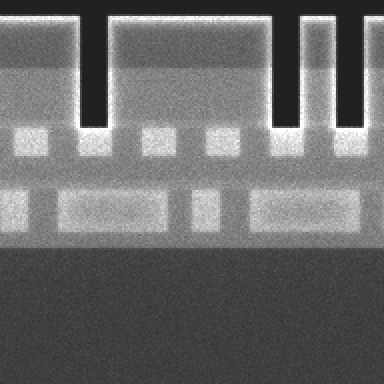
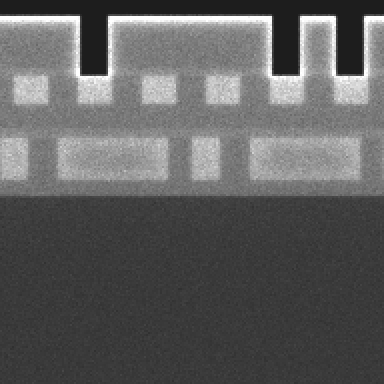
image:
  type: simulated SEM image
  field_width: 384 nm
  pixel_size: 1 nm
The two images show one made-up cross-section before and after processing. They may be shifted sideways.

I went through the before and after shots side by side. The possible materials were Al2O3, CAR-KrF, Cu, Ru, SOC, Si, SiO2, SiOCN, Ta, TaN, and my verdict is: removed, SOC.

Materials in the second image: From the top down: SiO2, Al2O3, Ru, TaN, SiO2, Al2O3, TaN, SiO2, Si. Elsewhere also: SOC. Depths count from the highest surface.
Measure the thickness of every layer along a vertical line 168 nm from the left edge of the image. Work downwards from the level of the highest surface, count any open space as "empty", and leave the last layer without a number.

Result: SiO2 52, Al2O3 8, TaN 28, SiO2 24, Al2O3 10, SiO2 58, Si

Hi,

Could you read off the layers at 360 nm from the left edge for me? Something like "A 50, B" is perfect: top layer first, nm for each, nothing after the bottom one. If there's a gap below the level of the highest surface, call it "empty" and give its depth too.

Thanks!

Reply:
empty 60, TaN 28, SiO2 24, Al2O3 10, SiO2 58, Si